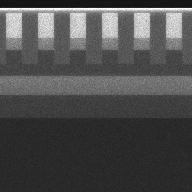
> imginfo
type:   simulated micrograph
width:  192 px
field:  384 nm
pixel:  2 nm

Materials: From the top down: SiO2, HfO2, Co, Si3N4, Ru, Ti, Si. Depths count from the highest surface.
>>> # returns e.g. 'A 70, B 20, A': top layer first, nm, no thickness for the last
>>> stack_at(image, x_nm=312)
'SiO2 112, Si3N4 24, Ru 38, Ti 46, Si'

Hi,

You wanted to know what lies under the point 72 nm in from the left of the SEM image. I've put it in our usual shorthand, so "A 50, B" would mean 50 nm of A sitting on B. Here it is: SiO2 112, Si3N4 24, Ru 38, Ti 46, Si